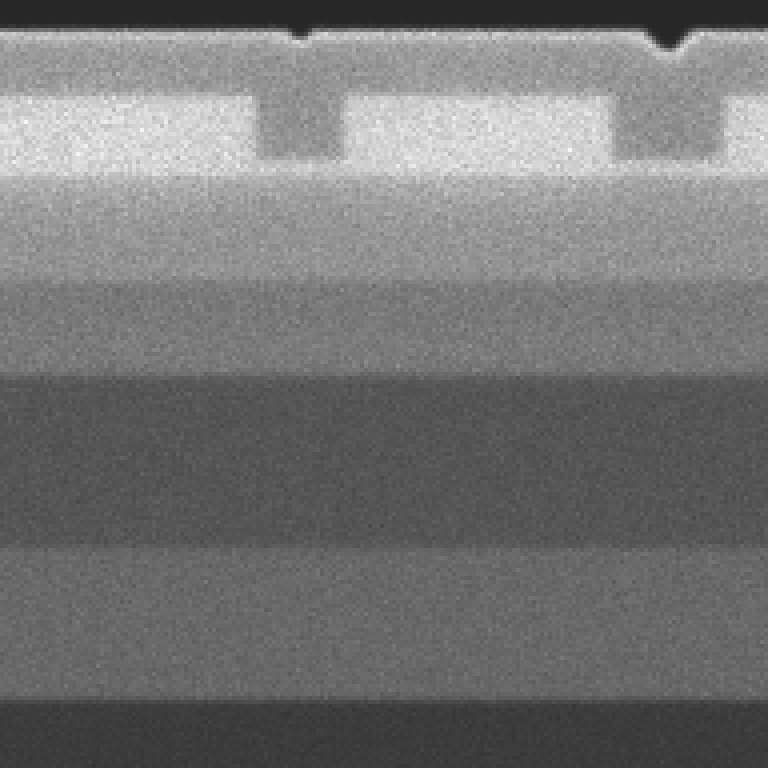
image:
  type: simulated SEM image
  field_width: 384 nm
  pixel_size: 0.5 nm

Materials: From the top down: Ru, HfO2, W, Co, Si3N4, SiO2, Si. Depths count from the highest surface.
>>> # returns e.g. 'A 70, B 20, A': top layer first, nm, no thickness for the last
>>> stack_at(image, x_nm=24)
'Ru 32, HfO2 40, W 52, Co 48, Si3N4 86, SiO2 76, Si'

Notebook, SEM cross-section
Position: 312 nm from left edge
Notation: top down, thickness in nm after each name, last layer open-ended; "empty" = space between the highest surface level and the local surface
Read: Ru 64, HfO2 8, W 52, Co 48, Si3N4 86, SiO2 76, Si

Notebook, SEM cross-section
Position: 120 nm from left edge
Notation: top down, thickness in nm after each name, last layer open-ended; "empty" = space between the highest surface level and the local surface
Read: Ru 32, HfO2 40, W 52, Co 48, Si3N4 86, SiO2 76, Si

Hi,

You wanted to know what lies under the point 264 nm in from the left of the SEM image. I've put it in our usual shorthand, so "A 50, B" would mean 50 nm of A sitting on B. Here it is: Ru 32, HfO2 40, W 52, Co 48, Si3N4 86, SiO2 76, Si